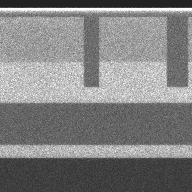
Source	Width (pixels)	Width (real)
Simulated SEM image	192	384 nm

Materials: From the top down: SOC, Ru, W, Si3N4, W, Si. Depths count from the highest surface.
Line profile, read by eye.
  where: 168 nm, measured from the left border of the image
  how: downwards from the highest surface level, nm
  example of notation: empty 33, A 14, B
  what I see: SOC 158, W 32, Si3N4 84, W 26, Si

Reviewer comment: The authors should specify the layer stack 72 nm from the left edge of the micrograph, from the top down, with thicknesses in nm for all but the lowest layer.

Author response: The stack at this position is SOC 18, Ru 90, W 82, Si3N4 84, W 26, Si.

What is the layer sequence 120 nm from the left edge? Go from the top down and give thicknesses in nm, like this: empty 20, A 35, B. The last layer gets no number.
SOC 18, Ru 90, W 82, Si3N4 84, W 26, Si